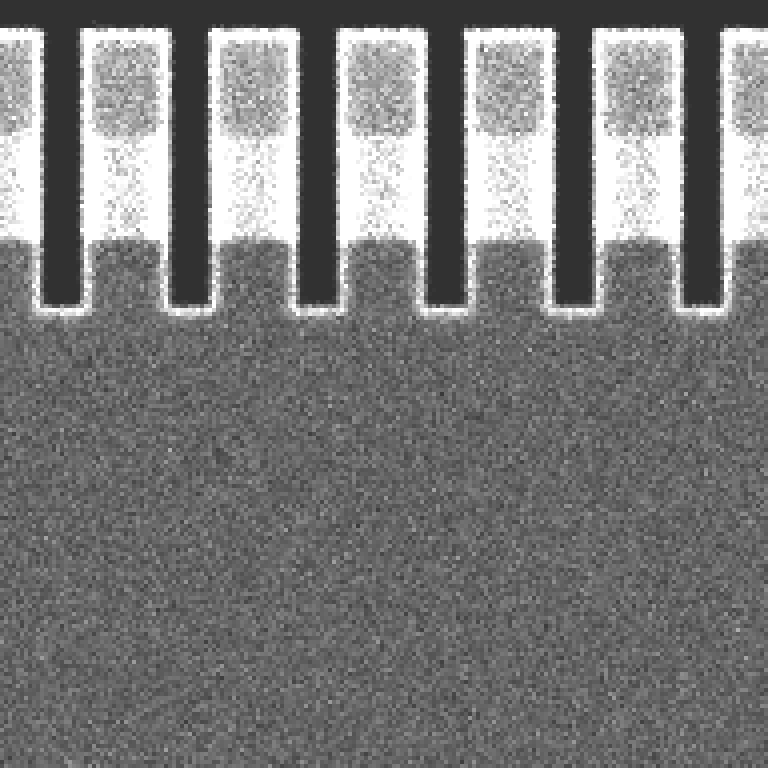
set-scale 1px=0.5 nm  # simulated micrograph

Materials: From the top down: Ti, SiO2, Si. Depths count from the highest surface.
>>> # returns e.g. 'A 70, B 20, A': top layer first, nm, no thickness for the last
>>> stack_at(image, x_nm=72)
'Ti 52, SiO2 52, Si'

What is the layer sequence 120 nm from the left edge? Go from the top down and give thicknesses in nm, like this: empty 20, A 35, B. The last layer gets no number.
Ti 52, SiO2 52, Si